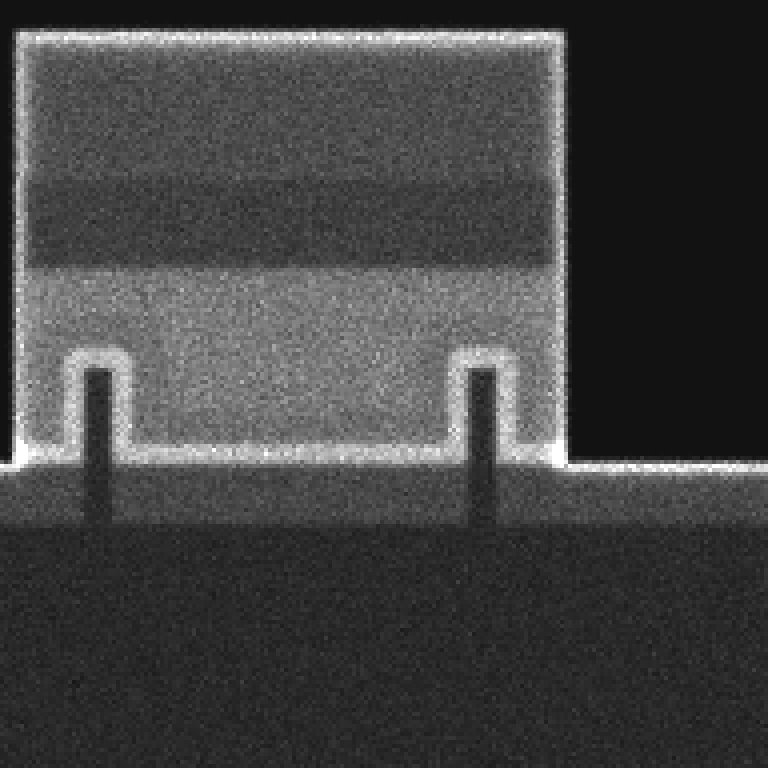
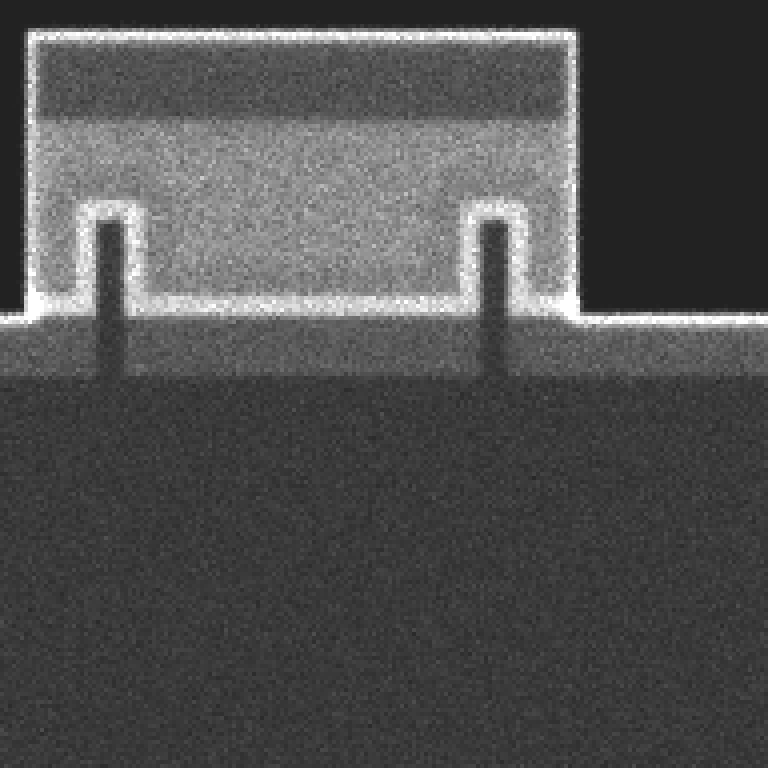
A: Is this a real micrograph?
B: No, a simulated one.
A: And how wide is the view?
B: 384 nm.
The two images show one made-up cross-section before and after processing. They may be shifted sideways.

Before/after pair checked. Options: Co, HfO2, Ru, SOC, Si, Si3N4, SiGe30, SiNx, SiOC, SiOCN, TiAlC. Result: removed SOC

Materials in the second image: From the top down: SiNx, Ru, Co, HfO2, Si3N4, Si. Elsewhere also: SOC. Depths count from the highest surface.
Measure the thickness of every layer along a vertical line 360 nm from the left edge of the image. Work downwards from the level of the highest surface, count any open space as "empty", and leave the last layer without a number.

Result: empty 142, Si3N4 30, Si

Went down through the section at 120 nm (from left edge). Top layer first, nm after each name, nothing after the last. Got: SiNx 44, Ru 72, Co 16, HfO2 10, Si3N4 30, Si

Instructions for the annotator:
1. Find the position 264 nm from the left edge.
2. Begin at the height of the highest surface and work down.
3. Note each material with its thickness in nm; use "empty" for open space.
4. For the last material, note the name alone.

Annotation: SiNx 44, Ru 24, Co 64, HfO2 10, Si3N4 30, Si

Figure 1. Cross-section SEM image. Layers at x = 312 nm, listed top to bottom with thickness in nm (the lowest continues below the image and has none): empty 142, Si3N4 30, Si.